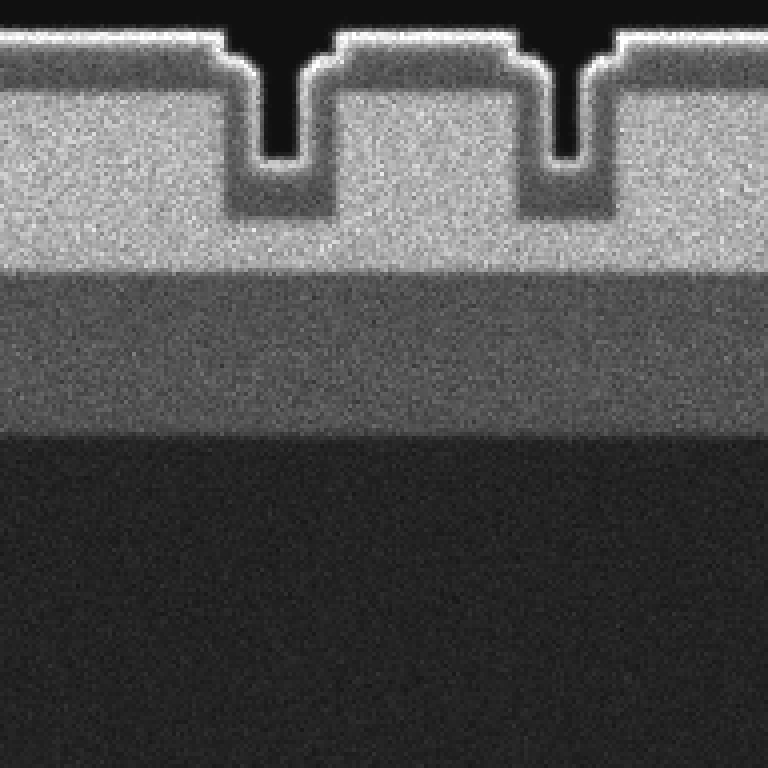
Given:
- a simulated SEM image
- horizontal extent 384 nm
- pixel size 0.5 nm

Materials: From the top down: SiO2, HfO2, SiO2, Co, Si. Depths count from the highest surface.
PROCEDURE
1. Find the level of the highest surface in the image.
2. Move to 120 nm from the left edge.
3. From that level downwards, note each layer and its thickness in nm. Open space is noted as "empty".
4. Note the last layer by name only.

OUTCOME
empty 12, SiO2 82, HfO2 26, SiO2 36, Co 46, Si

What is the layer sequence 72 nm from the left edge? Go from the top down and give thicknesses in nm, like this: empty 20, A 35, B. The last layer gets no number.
SiO2 30, HfO2 90, SiO2 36, Co 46, Si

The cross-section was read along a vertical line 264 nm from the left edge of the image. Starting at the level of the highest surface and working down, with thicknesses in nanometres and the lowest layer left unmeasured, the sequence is empty 12, SiO2 82, HfO2 26, SiO2 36, Co 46, Si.